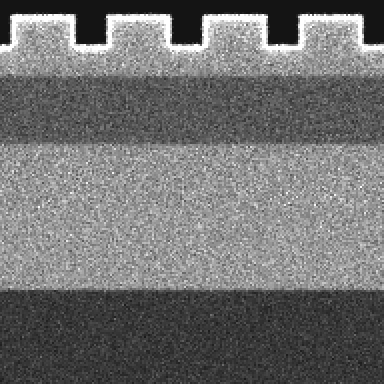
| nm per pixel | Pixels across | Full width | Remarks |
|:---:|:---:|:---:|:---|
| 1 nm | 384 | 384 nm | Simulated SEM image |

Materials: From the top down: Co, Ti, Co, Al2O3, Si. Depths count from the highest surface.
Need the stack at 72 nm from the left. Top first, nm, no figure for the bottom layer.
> Co 60, Ti 68, Co 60, Al2O3 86, Si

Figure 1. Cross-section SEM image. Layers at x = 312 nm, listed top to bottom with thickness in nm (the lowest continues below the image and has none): Co 60, Ti 68, Co 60, Al2O3 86, Si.